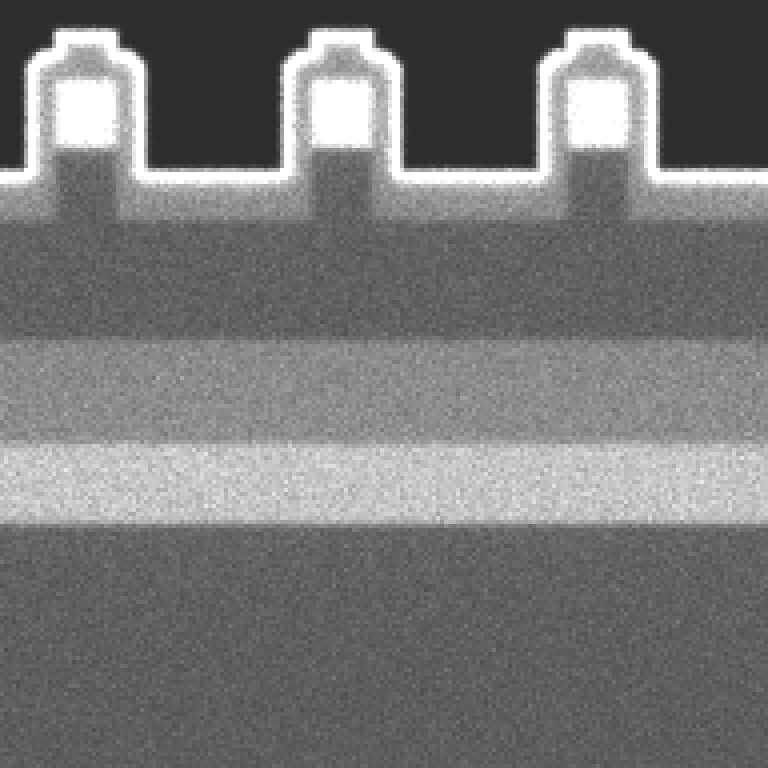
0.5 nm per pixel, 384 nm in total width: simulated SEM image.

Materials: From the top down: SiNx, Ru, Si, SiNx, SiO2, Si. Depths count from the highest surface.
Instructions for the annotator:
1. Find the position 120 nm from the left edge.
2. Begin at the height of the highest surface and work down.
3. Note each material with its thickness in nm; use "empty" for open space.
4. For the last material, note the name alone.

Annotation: empty 70, SiNx 24, Si 60, SiNx 52, SiO2 40, Si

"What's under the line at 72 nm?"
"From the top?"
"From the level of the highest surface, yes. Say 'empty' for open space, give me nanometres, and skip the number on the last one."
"empty 70, SiNx 24, Si 60, SiNx 52, SiO2 40, Si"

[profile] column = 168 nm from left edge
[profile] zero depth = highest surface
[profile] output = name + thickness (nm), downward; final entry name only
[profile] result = SiNx 24, Ru 34, Si 96, SiNx 52, SiO2 40, Si